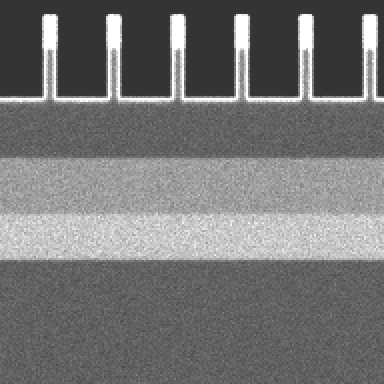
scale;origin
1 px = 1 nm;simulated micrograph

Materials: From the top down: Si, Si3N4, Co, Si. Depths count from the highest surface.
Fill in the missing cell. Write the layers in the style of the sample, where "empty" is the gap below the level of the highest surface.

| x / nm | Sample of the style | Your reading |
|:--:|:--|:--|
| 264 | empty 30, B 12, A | empty 82, Si 60, Si3N4 56, Co 46, Si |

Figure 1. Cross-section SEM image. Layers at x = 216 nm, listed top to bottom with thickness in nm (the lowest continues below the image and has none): empty 82, Si 60, Si3N4 56, Co 46, Si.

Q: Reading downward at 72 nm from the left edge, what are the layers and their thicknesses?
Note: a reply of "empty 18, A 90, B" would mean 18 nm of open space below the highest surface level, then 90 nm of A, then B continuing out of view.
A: empty 82, Si 60, Si3N4 56, Co 46, Si